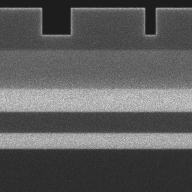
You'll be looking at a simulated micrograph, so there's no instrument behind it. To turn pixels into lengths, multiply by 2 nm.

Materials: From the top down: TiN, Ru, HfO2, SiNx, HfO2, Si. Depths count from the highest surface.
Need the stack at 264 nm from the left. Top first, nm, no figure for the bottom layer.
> TiN 84, Ru 78, HfO2 46, SiNx 42, HfO2 32, Si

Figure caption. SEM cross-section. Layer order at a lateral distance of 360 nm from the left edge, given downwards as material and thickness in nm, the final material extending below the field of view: TiN 84, Ru 78, HfO2 46, SiNx 42, HfO2 32, Si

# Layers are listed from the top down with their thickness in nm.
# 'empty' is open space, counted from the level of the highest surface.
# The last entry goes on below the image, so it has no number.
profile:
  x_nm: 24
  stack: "TiN 84, Ru 78, HfO2 46, SiNx 42, HfO2 32, Si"